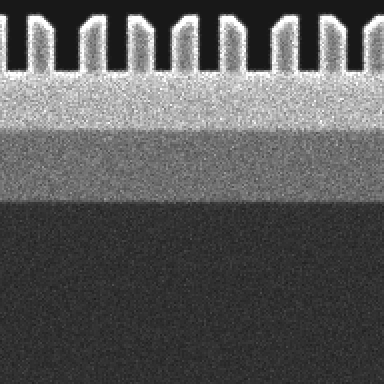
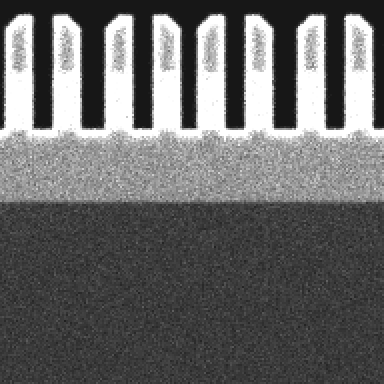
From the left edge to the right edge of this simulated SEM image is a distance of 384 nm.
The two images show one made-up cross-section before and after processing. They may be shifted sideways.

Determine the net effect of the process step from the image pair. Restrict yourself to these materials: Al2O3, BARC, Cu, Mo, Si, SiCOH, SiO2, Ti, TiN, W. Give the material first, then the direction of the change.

W: removed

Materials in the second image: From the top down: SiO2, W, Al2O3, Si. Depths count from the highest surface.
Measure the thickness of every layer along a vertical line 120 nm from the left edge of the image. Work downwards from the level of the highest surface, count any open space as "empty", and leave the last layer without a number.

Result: SiO2 56, W 58, Al2O3 72, Si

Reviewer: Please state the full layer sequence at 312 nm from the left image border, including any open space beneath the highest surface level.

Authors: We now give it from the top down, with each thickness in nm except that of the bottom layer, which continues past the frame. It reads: SiO2 56, W 58, Al2O3 72, Si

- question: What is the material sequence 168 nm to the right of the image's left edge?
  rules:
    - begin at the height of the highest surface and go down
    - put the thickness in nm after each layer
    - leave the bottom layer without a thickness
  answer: empty 2, SiO2 54, W 58, Al2O3 72, Si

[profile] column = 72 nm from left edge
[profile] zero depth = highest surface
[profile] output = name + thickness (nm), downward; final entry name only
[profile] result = empty 6, SiO2 50, W 58, Al2O3 72, Si